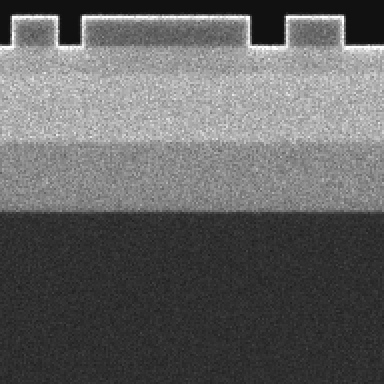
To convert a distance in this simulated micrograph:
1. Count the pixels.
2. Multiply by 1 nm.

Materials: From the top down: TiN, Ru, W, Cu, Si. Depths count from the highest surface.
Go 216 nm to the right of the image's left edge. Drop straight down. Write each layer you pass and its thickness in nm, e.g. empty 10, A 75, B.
TiN 30, Ru 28, W 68, Cu 70, Si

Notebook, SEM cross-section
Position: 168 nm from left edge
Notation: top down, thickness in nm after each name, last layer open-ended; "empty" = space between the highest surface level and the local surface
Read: TiN 30, Ru 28, W 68, Cu 70, Si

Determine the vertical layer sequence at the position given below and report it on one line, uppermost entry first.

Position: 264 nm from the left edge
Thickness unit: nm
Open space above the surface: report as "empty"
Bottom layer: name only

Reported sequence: empty 30, Ru 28, W 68, Cu 70, Si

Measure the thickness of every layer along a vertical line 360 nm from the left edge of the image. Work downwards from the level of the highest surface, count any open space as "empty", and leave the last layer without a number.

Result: empty 30, Ru 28, W 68, Cu 70, Si